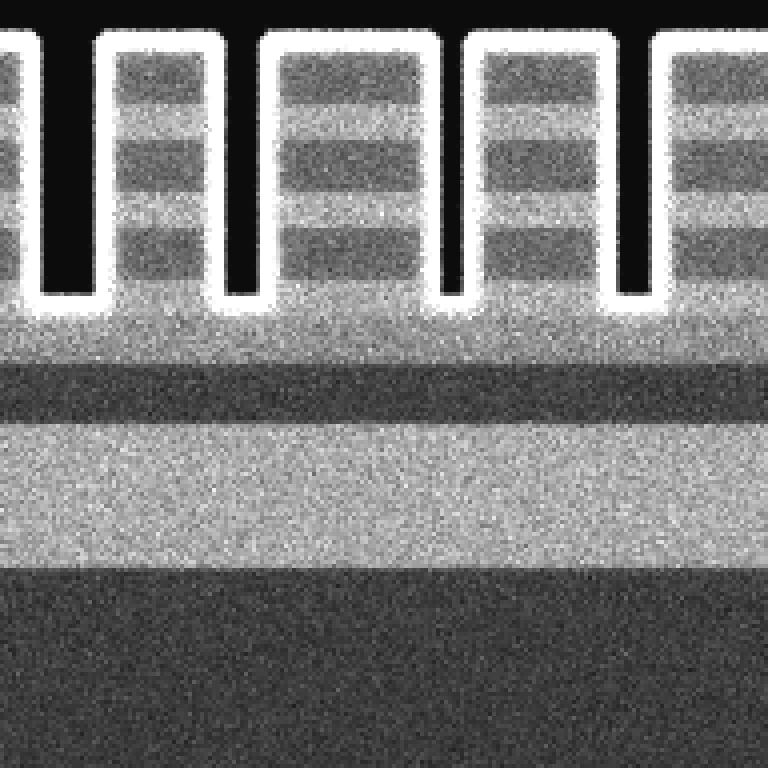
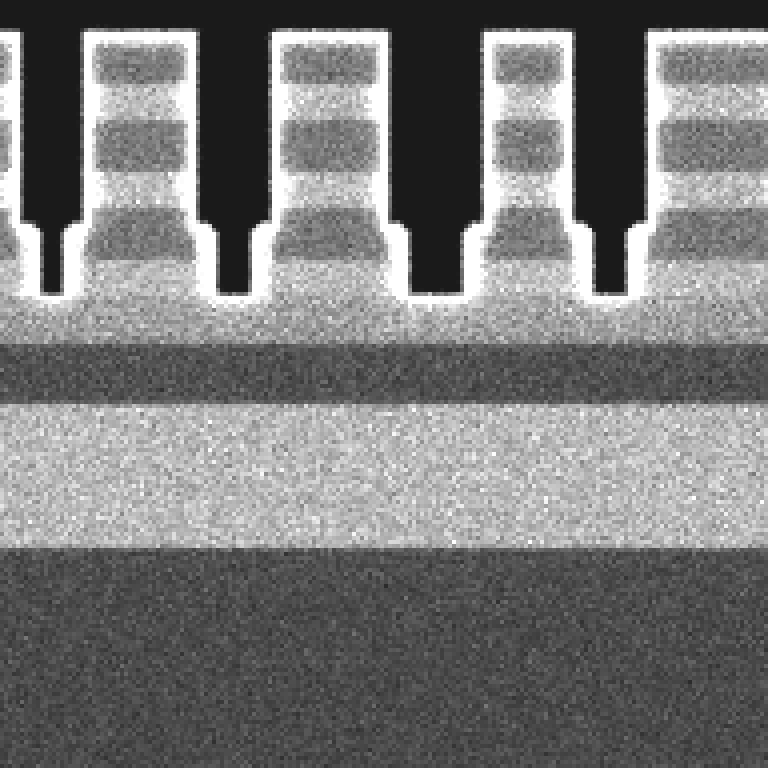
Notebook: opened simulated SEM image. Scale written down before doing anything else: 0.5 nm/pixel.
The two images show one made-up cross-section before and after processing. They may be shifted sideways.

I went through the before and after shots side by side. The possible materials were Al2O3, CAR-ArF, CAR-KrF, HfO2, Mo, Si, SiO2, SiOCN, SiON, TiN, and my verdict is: removed, Al2O3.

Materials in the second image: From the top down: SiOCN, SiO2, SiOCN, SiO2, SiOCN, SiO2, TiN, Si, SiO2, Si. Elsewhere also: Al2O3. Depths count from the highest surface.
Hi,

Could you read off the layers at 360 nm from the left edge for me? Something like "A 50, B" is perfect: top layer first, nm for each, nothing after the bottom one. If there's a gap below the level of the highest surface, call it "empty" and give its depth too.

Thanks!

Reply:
SiOCN 26, SiO2 18, SiOCN 26, SiO2 18, SiOCN 26, SiO2 18, TiN 24, Si 30, SiO2 72, Si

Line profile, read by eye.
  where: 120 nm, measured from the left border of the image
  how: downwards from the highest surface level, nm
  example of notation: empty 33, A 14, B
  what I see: empty 132, TiN 24, Si 30, SiO2 72, Si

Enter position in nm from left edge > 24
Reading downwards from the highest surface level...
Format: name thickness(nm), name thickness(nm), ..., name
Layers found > empty 132, TiN 24, Si 30, SiO2 72, Si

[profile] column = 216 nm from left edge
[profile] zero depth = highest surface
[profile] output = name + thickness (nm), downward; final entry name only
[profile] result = empty 132, TiN 24, Si 30, SiO2 72, Si